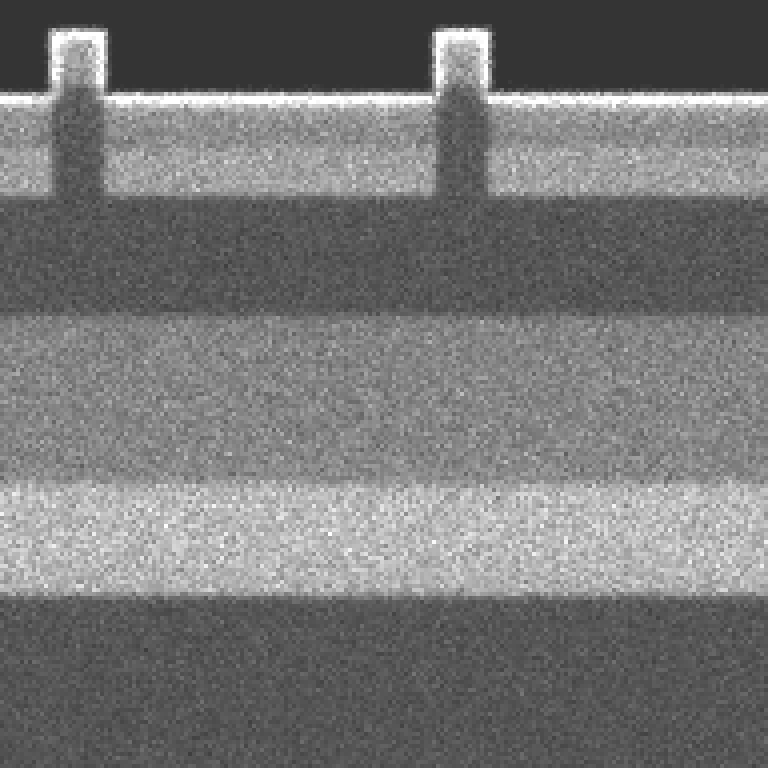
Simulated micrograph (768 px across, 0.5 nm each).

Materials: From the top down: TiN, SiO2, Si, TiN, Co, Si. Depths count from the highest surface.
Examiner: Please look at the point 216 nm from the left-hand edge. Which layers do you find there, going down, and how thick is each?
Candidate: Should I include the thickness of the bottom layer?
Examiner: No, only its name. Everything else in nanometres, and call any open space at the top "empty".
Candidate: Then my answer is empty 32, TiN 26, SiO2 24, Si 60, TiN 84, Co 56, Si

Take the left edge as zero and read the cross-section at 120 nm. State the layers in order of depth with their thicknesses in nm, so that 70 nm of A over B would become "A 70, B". empty 32, TiN 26, SiO2 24, Si 60, TiN 84, Co 56, Si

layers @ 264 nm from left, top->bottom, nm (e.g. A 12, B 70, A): empty 32, TiN 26, SiO2 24, Si 60, TiN 84, Co 56, Si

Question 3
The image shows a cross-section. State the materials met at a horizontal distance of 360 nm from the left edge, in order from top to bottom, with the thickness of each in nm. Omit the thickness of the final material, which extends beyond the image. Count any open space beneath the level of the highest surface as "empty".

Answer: empty 32, TiN 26, SiO2 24, Si 60, TiN 84, Co 56, Si